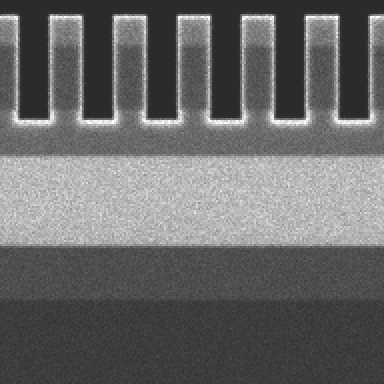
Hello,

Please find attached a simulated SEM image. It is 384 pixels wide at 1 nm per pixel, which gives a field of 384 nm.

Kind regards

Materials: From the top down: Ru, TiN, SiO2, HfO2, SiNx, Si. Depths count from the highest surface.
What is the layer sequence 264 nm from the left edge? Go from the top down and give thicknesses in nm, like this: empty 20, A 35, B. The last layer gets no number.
Ru 30, TiN 64, SiO2 46, HfO2 90, SiNx 54, Si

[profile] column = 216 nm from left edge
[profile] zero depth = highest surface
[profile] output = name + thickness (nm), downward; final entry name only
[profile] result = empty 104, SiO2 36, HfO2 90, SiNx 54, Si